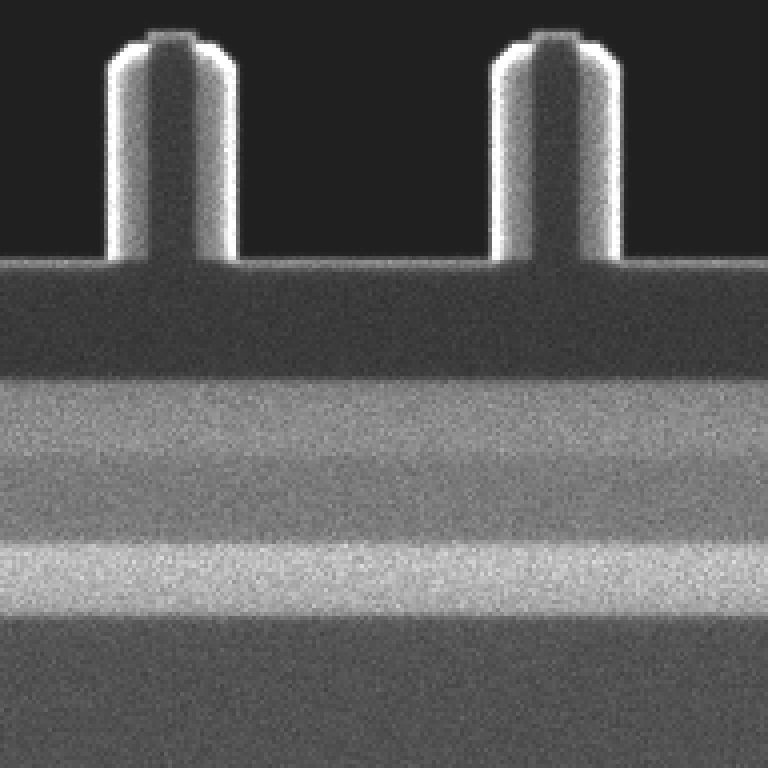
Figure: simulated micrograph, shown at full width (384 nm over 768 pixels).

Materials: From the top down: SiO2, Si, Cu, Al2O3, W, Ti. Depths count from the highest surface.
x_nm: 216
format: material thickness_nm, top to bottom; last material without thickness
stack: empty 114, Si 60, Cu 38, Al2O3 44, W 36, Ti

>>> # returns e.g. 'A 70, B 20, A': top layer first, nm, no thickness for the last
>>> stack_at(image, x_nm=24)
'empty 114, Si 60, Cu 38, Al2O3 44, W 36, Ti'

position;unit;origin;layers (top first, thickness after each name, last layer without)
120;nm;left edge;empty 114, Si 60, Cu 38, Al2O3 44, W 36, Ti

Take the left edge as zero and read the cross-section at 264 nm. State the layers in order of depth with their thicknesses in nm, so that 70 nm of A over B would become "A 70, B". empty 6, SiO2 108, Si 60, Cu 38, Al2O3 44, W 36, Ti